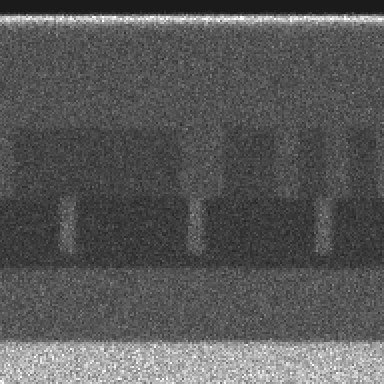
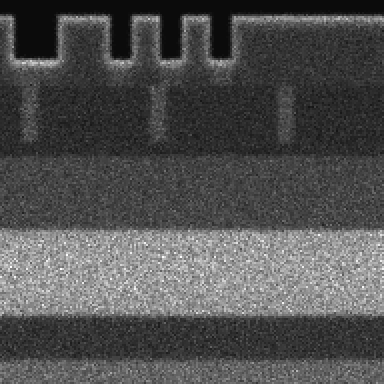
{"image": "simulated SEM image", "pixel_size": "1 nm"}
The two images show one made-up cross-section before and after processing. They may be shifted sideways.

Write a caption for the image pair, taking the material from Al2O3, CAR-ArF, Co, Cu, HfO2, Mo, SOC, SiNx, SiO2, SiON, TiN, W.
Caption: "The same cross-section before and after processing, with SiO2 removed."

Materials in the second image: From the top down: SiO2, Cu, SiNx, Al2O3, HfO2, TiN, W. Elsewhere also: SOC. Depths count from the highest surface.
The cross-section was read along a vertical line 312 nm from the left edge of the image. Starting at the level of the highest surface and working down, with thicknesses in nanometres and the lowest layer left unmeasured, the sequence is SOC 70, SiNx 70, Al2O3 74, HfO2 86, TiN 44, W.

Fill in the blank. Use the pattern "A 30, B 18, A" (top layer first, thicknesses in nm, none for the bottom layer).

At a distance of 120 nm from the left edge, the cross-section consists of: empty 44, SiO2 26, SiNx 70, Al2O3 74, HfO2 86, TiN 44, W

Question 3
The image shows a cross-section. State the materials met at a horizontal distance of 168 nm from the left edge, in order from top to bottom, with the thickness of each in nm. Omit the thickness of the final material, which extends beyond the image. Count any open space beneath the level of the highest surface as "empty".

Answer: empty 44, SiO2 26, SiNx 70, Al2O3 74, HfO2 86, TiN 44, W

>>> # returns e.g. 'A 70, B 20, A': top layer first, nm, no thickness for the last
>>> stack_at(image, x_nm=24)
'empty 44, SiO2 26, Cu 56, SiNx 14, Al2O3 74, HfO2 86, TiN 44, W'